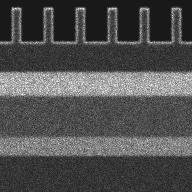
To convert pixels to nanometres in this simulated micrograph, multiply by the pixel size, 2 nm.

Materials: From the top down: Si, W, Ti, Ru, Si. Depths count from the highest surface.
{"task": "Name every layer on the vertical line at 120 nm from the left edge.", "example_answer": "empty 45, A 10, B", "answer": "empty 68, Si 60, W 48, Ti 82, Ru 38, Si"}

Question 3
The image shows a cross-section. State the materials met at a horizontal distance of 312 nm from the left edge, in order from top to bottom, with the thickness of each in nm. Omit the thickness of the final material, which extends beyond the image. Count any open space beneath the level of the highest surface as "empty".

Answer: empty 68, Si 60, W 48, Ti 82, Ru 38, Si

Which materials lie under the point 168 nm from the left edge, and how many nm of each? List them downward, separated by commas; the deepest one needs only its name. Si 128, W 48, Ti 82, Ru 38, Si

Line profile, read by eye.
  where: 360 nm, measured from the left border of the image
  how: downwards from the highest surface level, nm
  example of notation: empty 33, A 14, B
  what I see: Si 128, W 48, Ti 82, Ru 38, Si